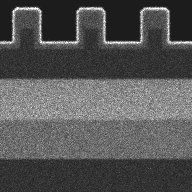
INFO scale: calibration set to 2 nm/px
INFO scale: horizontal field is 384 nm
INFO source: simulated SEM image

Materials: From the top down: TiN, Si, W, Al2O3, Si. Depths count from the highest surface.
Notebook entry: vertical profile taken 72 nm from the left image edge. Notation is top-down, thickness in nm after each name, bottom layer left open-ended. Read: TiN 82, Si 60, W 82, Al2O3 78, Si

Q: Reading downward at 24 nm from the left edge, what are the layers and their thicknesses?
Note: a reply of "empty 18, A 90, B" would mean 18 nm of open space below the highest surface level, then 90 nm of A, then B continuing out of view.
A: empty 68, TiN 14, Si 60, W 82, Al2O3 78, Si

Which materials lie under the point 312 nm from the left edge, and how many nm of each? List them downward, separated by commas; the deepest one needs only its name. TiN 42, Si 100, W 82, Al2O3 78, Si